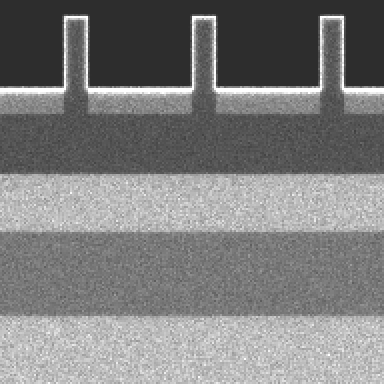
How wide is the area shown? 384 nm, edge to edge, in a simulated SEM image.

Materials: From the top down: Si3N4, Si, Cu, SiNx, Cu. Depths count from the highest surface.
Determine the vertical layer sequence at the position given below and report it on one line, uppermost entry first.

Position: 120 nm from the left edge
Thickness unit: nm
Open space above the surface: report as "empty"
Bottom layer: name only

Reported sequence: empty 72, Si3N4 26, Si 60, Cu 58, SiNx 84, Cu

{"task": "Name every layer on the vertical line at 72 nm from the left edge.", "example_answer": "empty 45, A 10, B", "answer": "Si 158, Cu 58, SiNx 84, Cu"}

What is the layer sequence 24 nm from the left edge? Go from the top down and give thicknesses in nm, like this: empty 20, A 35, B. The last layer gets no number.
empty 72, Si3N4 26, Si 60, Cu 58, SiNx 84, Cu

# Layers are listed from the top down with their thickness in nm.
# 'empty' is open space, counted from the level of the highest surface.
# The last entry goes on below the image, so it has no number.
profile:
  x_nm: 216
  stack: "empty 72, Si3N4 26, Si 60, Cu 58, SiNx 84, Cu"